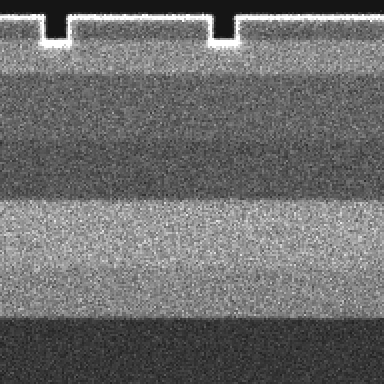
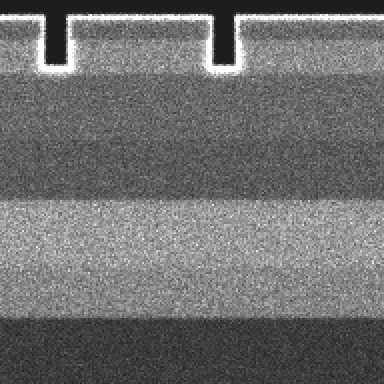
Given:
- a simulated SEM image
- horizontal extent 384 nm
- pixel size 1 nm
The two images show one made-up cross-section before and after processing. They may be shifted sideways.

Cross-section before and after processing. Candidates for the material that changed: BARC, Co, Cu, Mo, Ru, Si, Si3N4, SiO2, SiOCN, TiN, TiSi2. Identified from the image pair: SiO2 (removed).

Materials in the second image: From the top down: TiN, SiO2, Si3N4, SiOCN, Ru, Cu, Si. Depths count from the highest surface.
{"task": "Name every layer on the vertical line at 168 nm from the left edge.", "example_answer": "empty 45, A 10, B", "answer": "TiN 24, SiO2 34, Si3N4 66, SiOCN 60, Ru 68, Cu 50, Si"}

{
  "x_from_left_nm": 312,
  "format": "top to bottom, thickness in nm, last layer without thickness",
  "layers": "TiN 24, SiO2 34, Si3N4 66, SiOCN 60, Ru 68, Cu 50, Si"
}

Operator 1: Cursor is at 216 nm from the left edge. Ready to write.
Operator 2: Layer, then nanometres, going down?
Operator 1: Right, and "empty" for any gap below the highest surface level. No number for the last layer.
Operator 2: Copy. empty 50, SiO2 8, Si3N4 66, SiOCN 60, Ru 68, Cu 50, Si